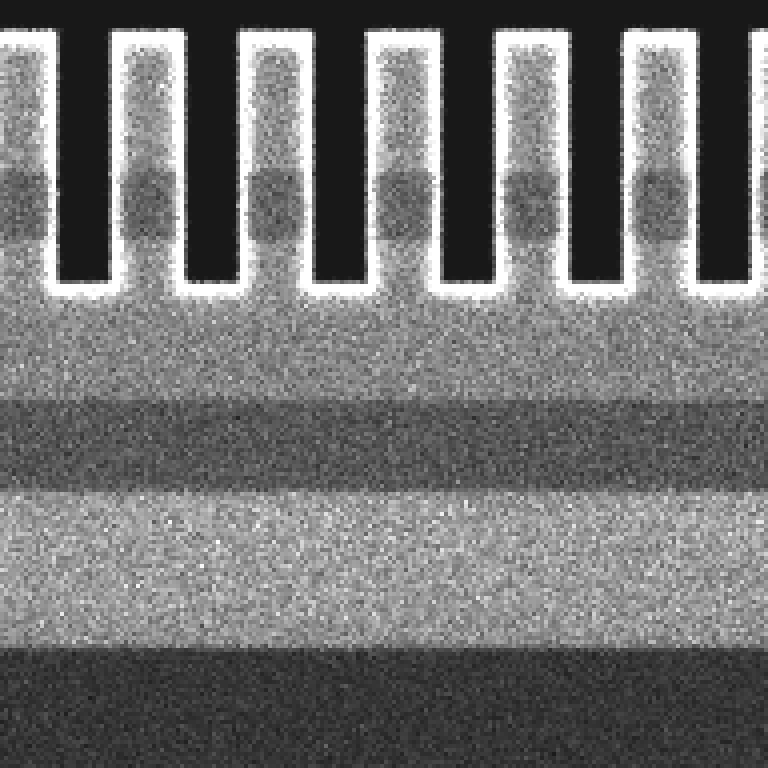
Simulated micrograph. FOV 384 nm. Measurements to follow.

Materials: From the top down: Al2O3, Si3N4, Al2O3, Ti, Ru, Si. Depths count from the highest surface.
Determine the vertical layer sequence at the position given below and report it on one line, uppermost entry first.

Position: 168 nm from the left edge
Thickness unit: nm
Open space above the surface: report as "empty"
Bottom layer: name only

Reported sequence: empty 126, Al2O3 58, Ti 46, Ru 78, Si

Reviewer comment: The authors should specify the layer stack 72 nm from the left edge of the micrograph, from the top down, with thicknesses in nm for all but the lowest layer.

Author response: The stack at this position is Al2O3 70, Si3N4 34, Al2O3 80, Ti 46, Ru 78, Si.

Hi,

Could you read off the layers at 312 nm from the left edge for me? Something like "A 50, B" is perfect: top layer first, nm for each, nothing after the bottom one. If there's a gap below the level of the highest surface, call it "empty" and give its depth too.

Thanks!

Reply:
Al2O3 70, Si3N4 34, Al2O3 80, Ti 46, Ru 78, Si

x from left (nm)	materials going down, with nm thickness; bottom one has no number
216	Al2O3 70, Si3N4 34, Al2O3 80, Ti 46, Ru 78, Si